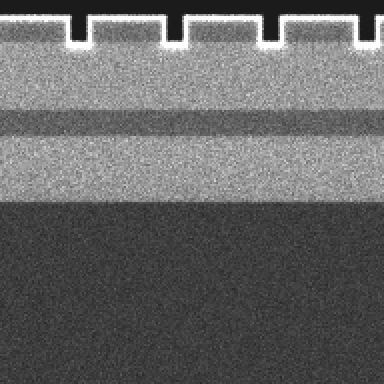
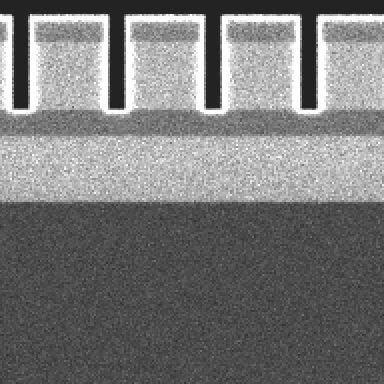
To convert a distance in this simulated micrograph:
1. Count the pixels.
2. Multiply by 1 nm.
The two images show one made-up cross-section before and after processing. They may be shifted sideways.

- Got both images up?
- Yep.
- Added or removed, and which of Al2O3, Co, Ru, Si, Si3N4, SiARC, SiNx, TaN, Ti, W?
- removed, Al2O3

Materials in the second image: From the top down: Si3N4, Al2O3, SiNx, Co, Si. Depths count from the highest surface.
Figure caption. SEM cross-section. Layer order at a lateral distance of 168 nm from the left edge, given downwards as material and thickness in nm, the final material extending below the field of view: Si3N4 26, Al2O3 68, SiNx 26, Co 66, Si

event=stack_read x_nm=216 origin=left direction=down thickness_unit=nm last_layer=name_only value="empty 94, SiNx 26, Co 66, Si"